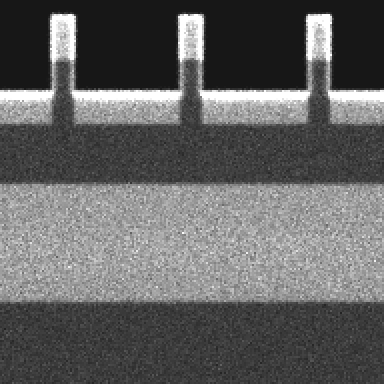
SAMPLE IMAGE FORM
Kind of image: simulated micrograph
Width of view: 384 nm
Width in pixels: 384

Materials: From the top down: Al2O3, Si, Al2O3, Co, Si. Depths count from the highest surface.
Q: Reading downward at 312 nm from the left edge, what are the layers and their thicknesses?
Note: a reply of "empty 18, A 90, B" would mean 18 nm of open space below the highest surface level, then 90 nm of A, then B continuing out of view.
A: Co 44, Si 124, Al2O3 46, Co 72, Si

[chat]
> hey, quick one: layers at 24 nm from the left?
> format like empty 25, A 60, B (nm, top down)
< empty 76, Al2O3 32, Si 60, Al2O3 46, Co 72, Si